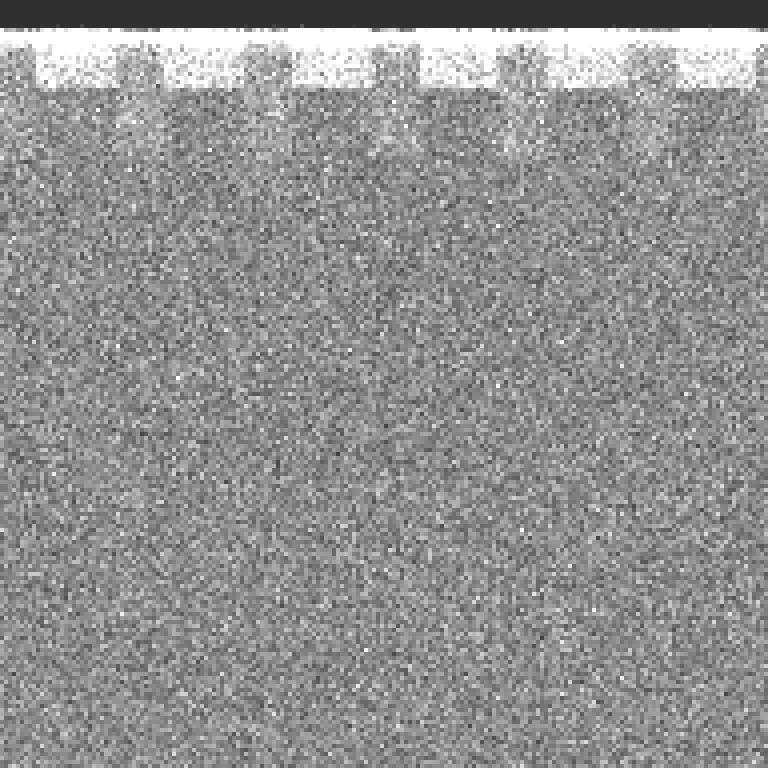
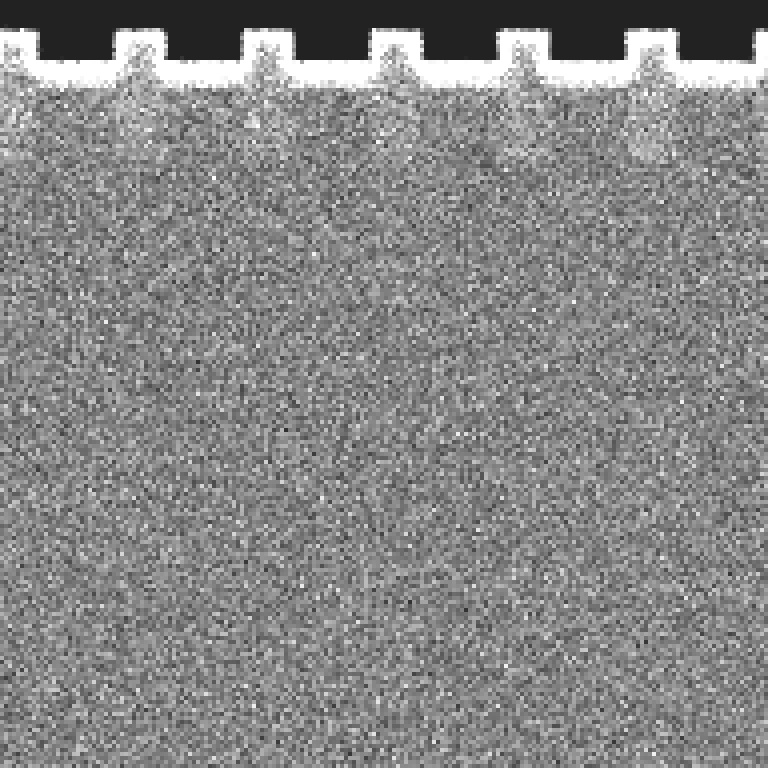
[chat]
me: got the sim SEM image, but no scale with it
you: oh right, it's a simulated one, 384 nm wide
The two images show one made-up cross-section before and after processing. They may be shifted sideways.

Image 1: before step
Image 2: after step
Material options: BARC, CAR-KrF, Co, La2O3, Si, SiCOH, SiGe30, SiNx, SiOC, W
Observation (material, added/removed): SiNx, removed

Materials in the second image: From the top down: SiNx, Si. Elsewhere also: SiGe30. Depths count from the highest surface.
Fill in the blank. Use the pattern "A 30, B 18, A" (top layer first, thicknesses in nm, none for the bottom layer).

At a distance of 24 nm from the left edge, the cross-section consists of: empty 16, SiNx 12, Si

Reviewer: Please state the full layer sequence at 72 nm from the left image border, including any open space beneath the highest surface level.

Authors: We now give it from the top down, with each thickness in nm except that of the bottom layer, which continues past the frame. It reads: SiGe30 64, Si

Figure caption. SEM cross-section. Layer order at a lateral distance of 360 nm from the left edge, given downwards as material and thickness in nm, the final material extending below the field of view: empty 16, SiNx 12, Si